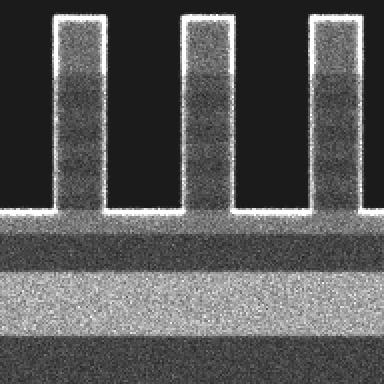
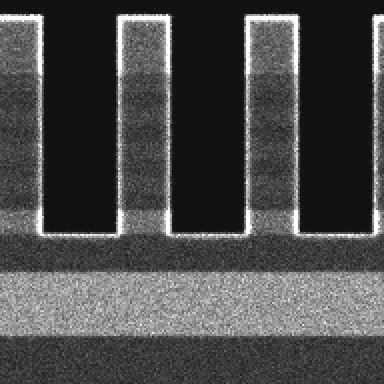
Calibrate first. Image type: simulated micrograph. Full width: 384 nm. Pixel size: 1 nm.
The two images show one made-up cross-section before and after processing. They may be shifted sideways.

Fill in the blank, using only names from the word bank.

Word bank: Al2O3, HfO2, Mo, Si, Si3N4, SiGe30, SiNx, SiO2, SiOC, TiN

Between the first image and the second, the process removed Si3N4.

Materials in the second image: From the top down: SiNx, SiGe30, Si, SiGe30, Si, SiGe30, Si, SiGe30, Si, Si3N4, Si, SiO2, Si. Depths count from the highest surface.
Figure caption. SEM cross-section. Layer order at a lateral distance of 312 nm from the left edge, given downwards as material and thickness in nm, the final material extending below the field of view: empty 218, Si 38, SiO2 64, Si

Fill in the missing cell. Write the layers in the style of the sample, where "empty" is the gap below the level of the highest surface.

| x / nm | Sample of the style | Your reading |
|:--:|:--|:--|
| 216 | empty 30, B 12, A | empty 218, Si 38, SiO2 64, Si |